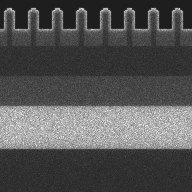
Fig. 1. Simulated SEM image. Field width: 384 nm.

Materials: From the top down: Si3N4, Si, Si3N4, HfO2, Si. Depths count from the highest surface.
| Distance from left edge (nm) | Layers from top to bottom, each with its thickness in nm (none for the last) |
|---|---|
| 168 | empty 4, Si3N4 72, Si 60, Si3N4 60, HfO2 86, Si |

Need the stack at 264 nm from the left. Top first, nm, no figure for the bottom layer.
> empty 4, Si3N4 72, Si 60, Si3N4 60, HfO2 86, Si